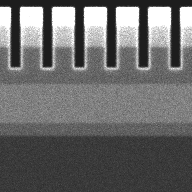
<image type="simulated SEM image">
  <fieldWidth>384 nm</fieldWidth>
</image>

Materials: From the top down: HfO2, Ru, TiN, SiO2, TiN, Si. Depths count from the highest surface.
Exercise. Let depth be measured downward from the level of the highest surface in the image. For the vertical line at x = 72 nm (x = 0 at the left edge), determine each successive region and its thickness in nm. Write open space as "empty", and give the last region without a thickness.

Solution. HfO2 36, Ru 42, TiN 74, SiO2 78, TiN 26, Si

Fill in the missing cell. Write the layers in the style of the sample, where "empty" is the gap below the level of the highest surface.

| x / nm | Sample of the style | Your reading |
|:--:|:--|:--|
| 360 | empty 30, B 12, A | empty 120, TiN 32, SiO2 78, TiN 26, Si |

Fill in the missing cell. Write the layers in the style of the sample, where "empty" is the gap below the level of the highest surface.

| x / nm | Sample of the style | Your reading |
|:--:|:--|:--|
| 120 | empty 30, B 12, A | HfO2 36, Ru 42, TiN 74, SiO2 78, TiN 26, Si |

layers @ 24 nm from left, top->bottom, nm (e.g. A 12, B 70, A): empty 120, TiN 32, SiO2 78, TiN 26, Si